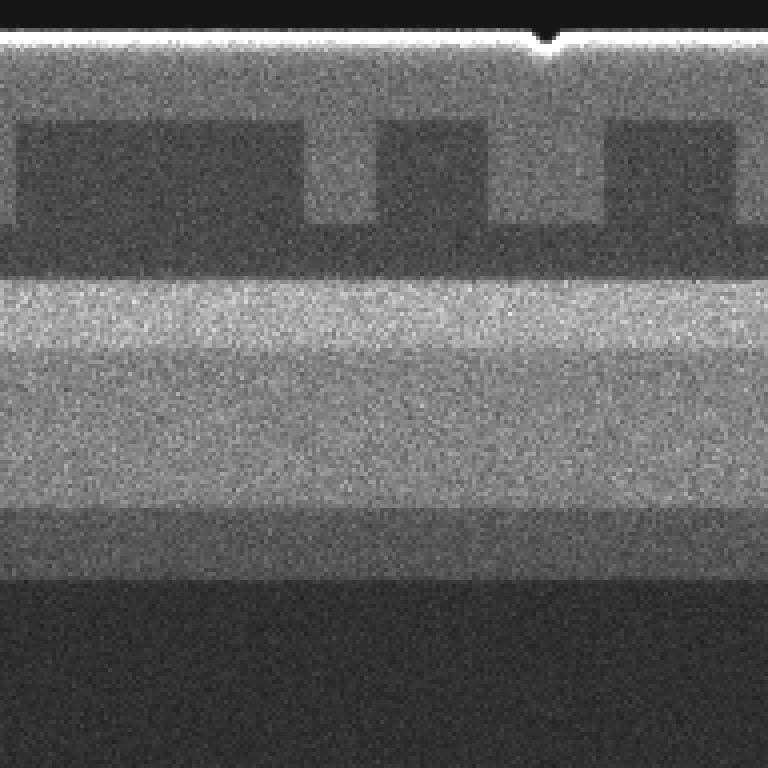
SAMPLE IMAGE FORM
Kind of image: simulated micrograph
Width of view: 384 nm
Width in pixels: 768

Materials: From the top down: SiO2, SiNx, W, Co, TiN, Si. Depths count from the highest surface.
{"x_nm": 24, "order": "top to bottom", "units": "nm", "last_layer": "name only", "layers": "SiO2 44, SiNx 80, W 34, Co 80, TiN 36, Si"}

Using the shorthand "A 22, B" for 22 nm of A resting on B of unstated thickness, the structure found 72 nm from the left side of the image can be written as SiO2 44, SiNx 80, W 34, Co 80, TiN 36, Si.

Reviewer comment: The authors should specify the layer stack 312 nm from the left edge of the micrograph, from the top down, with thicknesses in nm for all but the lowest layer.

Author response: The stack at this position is SiO2 44, SiNx 80, W 34, Co 80, TiN 36, Si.